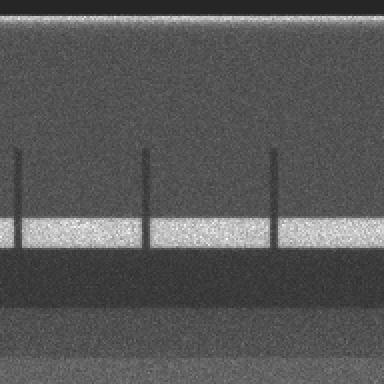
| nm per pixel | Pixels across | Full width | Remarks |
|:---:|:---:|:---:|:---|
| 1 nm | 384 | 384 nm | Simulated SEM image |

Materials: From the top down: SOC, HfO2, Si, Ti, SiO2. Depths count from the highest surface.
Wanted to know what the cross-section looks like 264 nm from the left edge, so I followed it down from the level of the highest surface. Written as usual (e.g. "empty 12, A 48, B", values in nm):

SOC 202, HfO2 30, Si 60, Ti 50, SiO2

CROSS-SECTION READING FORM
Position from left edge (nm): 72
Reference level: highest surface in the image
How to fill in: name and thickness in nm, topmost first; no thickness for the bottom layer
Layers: SOC 202, HfO2 30, Si 60, Ti 50, SiO2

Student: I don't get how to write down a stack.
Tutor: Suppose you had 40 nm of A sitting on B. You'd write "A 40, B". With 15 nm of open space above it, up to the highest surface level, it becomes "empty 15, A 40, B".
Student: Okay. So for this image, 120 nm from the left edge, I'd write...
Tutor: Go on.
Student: SOC 202, HfO2 30, Si 60, Ti 50, SiO2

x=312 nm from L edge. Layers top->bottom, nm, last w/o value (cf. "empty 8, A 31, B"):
SOC 202, HfO2 30, Si 60, Ti 50, SiO2